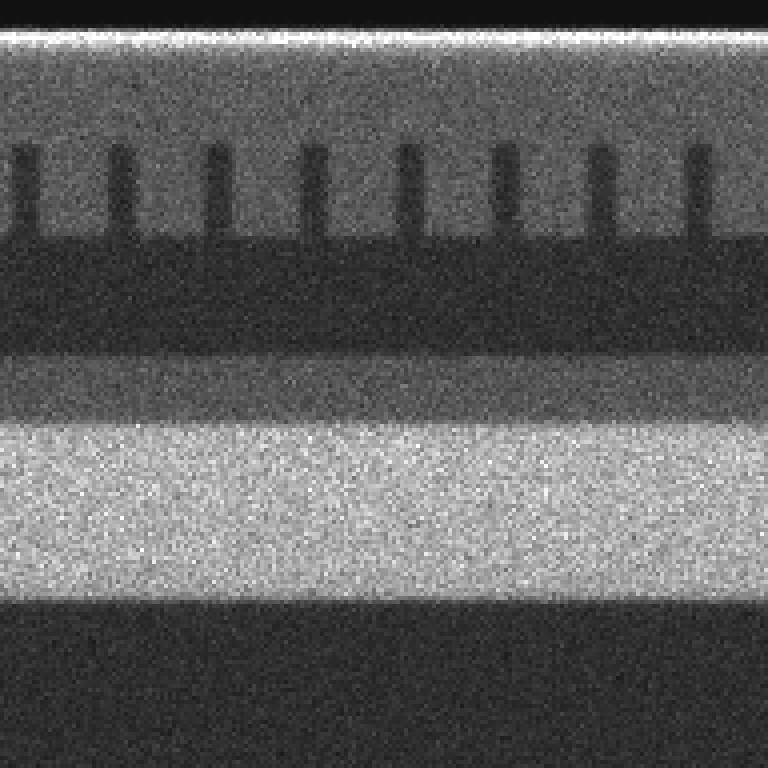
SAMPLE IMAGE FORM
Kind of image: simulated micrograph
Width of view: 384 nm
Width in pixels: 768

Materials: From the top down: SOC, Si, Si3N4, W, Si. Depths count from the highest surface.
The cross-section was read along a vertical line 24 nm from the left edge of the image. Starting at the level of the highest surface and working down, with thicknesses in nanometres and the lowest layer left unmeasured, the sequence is SOC 102, Si 60, Si3N4 34, W 88, Si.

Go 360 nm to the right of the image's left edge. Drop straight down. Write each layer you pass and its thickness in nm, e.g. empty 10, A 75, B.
SOC 102, Si 60, Si3N4 34, W 88, Si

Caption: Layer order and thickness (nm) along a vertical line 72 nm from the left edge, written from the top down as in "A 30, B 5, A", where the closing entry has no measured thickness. SOC 102, Si 60, Si3N4 34, W 88, Si